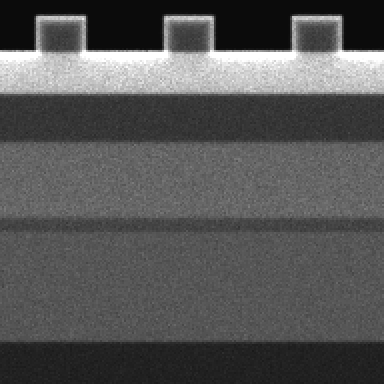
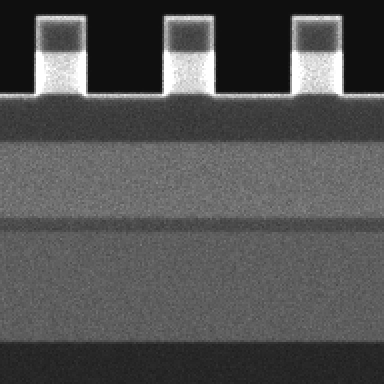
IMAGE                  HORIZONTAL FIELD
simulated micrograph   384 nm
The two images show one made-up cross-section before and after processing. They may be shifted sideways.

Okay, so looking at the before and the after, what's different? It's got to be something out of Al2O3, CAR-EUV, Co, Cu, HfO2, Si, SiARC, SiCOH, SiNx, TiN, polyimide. HfO2, removed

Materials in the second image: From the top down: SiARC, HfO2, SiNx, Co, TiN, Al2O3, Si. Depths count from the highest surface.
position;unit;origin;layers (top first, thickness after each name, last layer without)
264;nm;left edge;empty 78, SiNx 48, Co 76, TiN 14, Al2O3 110, Si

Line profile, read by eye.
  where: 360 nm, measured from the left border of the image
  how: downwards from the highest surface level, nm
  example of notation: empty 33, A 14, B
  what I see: empty 78, SiNx 48, Co 76, TiN 14, Al2O3 110, Si